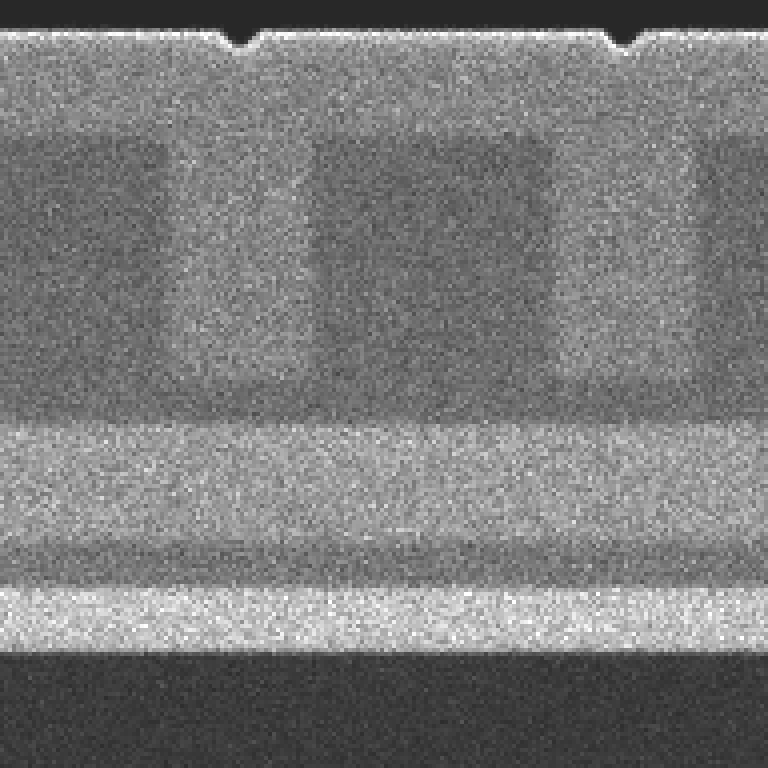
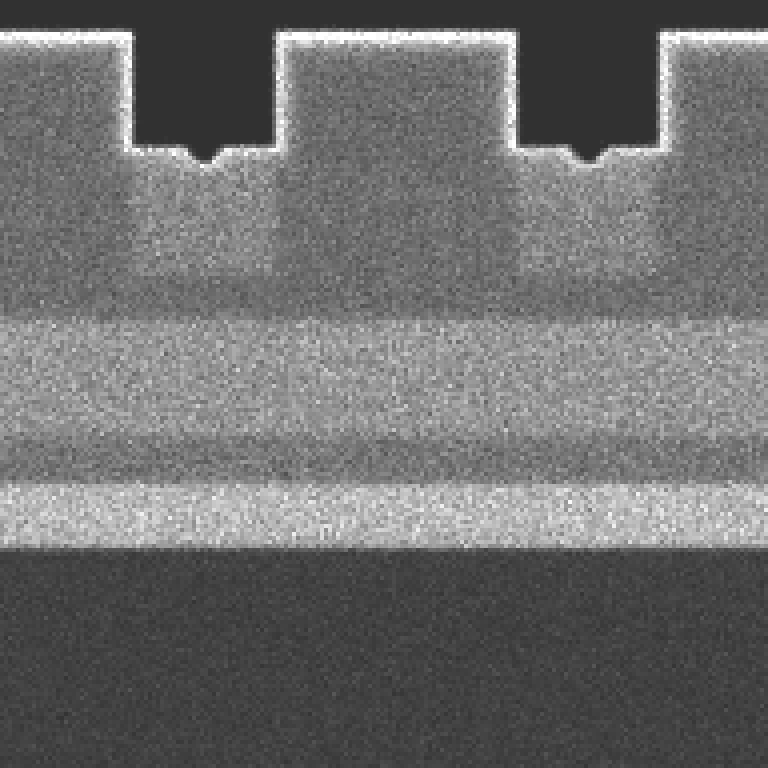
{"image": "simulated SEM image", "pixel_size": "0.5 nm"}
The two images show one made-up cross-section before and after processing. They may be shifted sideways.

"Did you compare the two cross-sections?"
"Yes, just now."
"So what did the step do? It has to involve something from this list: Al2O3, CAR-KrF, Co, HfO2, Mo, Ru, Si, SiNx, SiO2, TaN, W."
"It removed Ru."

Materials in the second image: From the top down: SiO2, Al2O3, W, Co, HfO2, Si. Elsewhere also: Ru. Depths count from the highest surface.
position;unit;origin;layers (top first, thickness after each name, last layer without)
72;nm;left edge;empty 58, Ru 64, Al2O3 22, W 58, Co 24, HfO2 32, Si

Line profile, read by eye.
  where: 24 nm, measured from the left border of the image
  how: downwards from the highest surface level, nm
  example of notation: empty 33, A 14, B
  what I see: SiO2 66, Al2O3 78, W 58, Co 24, HfO2 32, Si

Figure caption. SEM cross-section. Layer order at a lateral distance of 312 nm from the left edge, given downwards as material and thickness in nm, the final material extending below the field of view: empty 58, Ru 64, Al2O3 22, W 58, Co 24, HfO2 32, Si